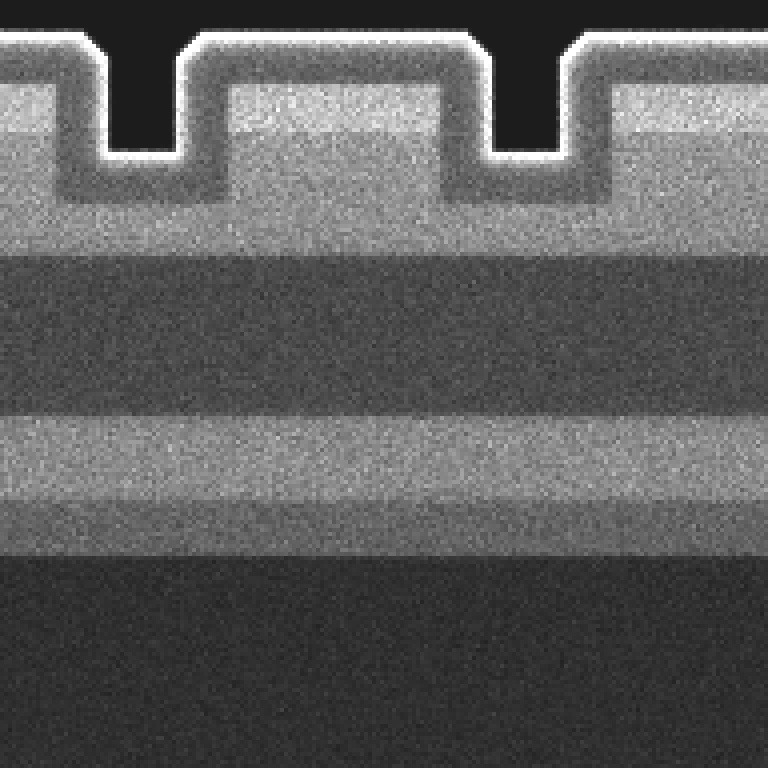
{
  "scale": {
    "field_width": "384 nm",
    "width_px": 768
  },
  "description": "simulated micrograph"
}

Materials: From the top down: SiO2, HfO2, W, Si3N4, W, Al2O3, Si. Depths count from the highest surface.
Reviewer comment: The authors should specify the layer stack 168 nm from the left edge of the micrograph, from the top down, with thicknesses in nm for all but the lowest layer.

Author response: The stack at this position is SiO2 26, HfO2 24, W 62, Si3N4 80, W 42, Al2O3 28, Si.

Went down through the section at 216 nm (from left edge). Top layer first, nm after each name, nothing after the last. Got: SiO2 26, HfO2 24, W 62, Si3N4 80, W 42, Al2O3 28, Si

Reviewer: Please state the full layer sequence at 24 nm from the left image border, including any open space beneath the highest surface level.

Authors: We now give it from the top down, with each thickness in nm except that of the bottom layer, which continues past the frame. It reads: SiO2 26, HfO2 24, W 62, Si3N4 80, W 42, Al2O3 28, Si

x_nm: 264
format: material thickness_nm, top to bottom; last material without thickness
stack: empty 60, SiO2 26, W 26, Si3N4 80, W 42, Al2O3 28, Si